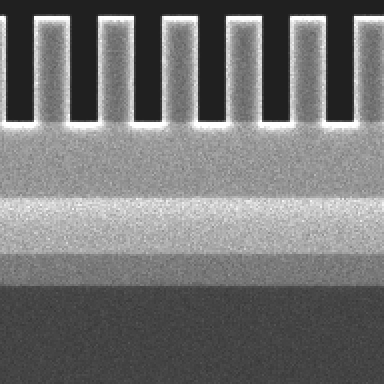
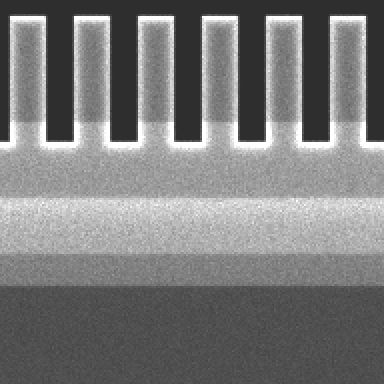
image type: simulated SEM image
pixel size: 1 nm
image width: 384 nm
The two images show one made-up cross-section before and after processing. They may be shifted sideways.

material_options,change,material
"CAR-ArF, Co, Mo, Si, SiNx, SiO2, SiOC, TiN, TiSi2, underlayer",removed,SiO2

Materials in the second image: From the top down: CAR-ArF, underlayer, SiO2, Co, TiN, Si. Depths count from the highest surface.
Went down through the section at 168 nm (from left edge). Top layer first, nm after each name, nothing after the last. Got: CAR-ArF 70, underlayer 36, SiO2 76, Co 56, TiN 32, Si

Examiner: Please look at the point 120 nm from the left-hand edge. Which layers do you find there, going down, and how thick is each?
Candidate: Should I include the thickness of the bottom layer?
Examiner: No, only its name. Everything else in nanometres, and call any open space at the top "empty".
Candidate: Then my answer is empty 126, SiO2 56, Co 56, TiN 32, Si